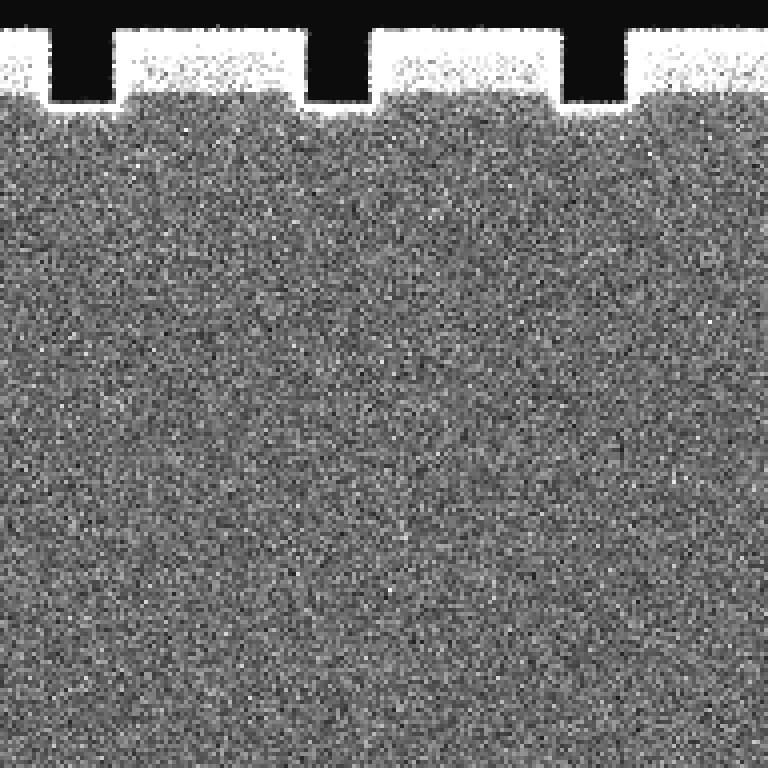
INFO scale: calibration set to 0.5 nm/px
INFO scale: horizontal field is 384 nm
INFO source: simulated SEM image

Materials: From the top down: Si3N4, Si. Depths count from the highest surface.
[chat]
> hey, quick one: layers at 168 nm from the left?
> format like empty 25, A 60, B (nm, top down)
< empty 36, Si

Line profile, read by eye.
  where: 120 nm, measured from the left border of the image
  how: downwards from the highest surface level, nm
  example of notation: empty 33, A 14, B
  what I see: Si3N4 30, Si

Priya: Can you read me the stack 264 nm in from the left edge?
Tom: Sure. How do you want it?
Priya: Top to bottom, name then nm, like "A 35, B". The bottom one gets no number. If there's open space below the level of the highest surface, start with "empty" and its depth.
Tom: Si3N4 30, Si